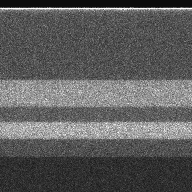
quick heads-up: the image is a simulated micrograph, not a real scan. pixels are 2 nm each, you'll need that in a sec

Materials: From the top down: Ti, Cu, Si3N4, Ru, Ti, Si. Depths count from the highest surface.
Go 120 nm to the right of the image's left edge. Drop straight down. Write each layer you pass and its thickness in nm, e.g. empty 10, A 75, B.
Ti 144, Cu 54, Si3N4 30, Ru 34, Ti 36, Si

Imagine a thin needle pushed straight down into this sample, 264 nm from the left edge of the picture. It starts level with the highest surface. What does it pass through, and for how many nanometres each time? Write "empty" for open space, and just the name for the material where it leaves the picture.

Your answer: Ti 144, Cu 54, Si3N4 30, Ru 34, Ti 36, Si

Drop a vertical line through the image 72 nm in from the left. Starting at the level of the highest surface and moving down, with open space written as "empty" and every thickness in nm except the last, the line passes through Ti 144, Cu 54, Si3N4 30, Ru 34, Ti 36, Si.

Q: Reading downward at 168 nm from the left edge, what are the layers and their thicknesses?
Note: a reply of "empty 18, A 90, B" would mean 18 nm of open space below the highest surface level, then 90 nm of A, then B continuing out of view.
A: Ti 144, Cu 54, Si3N4 30, Ru 34, Ti 36, Si